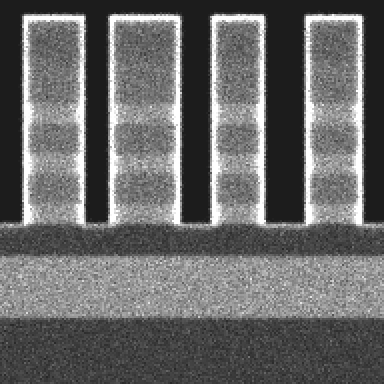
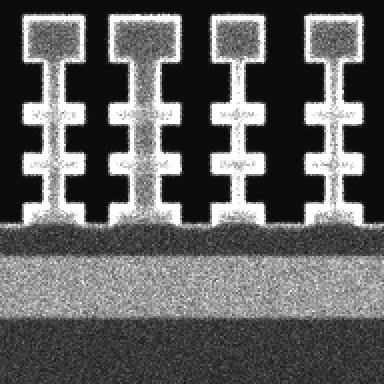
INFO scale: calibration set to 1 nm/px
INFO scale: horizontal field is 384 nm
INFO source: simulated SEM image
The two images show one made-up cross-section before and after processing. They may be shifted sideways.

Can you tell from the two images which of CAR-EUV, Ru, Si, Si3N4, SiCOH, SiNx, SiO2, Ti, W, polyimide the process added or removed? Yes, it removed Si3N4.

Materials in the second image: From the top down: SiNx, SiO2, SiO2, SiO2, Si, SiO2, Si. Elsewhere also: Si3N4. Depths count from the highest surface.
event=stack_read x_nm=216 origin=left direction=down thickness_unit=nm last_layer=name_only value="SiNx 46, empty 42, SiO2 20, empty 30, SiO2 20, empty 30, SiO2 20, Si 32, SiO2 62, Si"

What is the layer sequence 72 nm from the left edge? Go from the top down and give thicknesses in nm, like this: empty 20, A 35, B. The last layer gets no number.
SiNx 46, empty 42, SiO2 20, empty 30, SiO2 20, empty 30, SiO2 20, Si 32, SiO2 62, Si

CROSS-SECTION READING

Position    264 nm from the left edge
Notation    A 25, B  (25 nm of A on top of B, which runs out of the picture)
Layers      empty 208, Si 32, SiO2 62, Si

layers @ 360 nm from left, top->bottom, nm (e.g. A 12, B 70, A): SiNx 46, empty 42, SiO2 20, empty 30, SiO2 20, empty 30, SiO2 20, Si 32, SiO2 62, Si